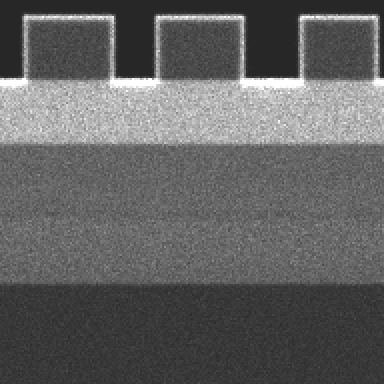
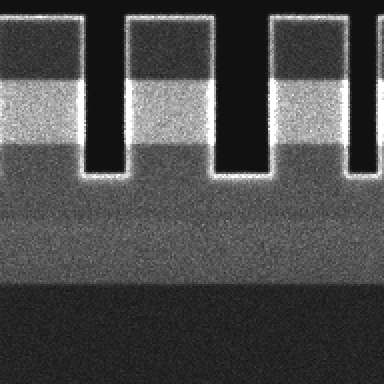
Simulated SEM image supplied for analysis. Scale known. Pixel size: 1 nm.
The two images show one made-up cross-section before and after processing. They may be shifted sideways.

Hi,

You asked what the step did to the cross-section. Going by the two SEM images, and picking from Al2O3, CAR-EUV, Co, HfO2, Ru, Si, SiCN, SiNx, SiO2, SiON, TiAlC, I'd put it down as HfO2 and SiO2, removed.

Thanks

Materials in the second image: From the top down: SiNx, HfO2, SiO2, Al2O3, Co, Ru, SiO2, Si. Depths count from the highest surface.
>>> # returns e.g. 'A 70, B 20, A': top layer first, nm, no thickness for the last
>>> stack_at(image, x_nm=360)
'empty 158, SiO2 10, Al2O3 26, Co 10, Ru 50, SiO2 14, Si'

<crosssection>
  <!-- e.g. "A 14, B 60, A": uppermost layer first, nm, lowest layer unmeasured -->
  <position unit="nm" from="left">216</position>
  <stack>empty 158, SiO2 10, Al2O3 26, Co 10, Ru 50, SiO2 14, Si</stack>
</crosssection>